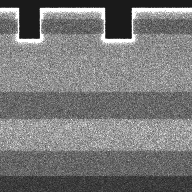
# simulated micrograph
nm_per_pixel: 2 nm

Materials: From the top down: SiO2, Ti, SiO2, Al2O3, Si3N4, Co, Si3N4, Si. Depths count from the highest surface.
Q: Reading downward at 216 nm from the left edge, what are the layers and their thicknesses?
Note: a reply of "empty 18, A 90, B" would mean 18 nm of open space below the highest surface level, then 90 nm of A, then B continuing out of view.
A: empty 62, SiO2 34, Al2O3 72, Si3N4 54, Co 64, Si3N4 50, Si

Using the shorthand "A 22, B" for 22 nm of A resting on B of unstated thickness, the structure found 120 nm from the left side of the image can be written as SiO2 22, Ti 30, SiO2 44, Al2O3 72, Si3N4 54, Co 64, Si3N4 50, Si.